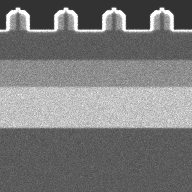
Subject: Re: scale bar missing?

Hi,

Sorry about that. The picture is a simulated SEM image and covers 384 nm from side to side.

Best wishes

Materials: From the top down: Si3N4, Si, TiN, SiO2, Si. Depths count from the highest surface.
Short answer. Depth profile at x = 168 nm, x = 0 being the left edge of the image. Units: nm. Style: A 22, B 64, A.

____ empty 44, Si 60, TiN 54, SiO2 82, Si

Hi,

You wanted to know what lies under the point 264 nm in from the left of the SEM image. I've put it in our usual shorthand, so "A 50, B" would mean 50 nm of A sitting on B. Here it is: empty 44, Si 60, TiN 54, SiO2 82, Si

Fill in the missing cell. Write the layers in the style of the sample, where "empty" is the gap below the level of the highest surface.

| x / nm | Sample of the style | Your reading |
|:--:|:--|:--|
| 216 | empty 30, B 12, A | empty 6, Si3N4 38, Si 60, TiN 54, SiO2 82, Si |